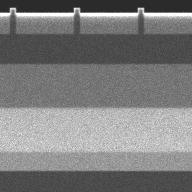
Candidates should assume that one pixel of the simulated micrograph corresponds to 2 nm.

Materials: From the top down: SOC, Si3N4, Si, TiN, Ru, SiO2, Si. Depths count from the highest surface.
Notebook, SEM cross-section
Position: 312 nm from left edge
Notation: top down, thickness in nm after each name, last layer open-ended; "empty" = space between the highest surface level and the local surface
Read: empty 10, SOC 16, Si3N4 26, Si 60, TiN 88, Ru 88, SiO2 38, Si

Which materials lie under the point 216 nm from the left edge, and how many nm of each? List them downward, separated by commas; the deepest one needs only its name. empty 10, SOC 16, Si3N4 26, Si 60, TiN 88, Ru 88, SiO2 38, Si